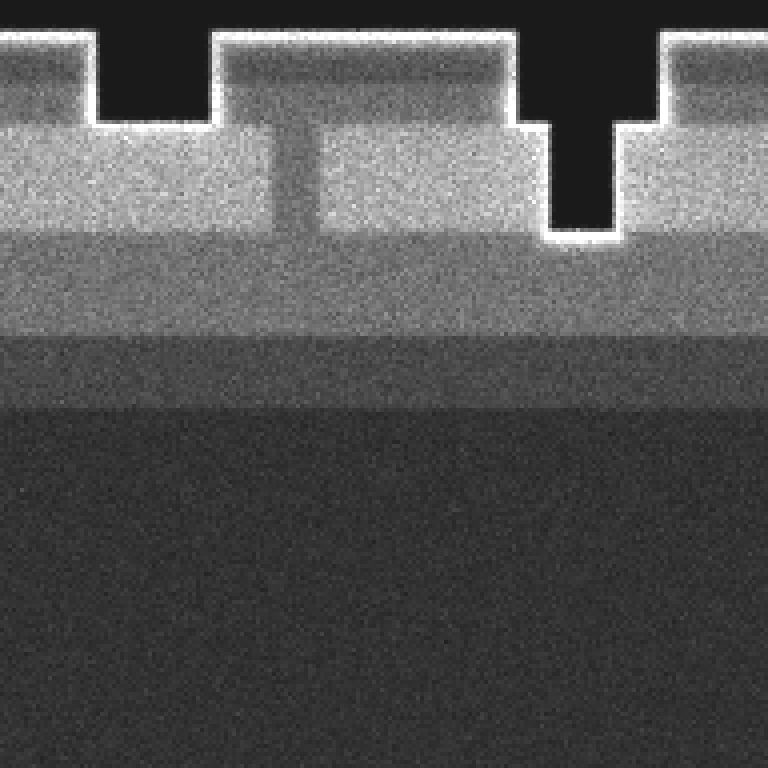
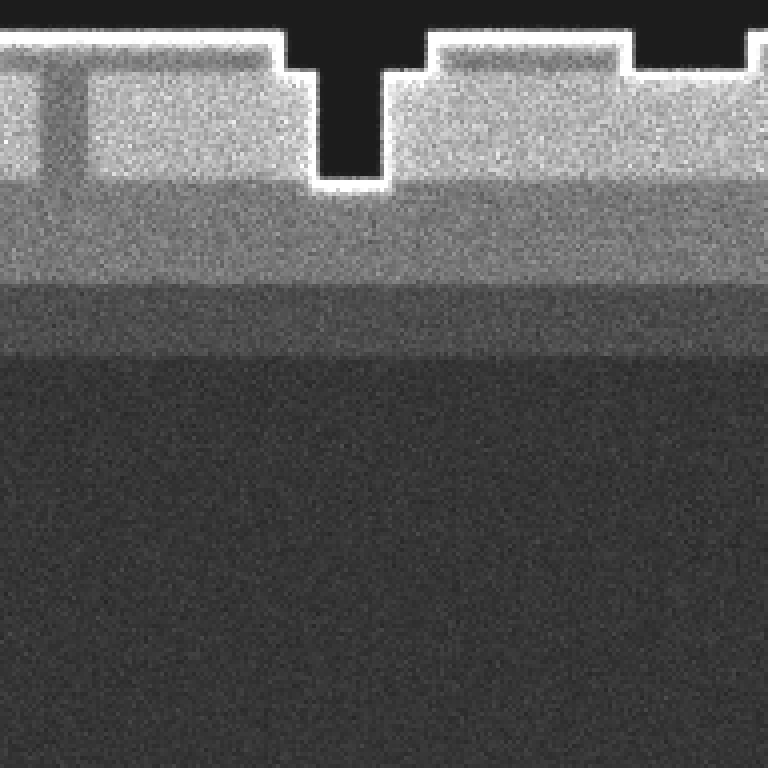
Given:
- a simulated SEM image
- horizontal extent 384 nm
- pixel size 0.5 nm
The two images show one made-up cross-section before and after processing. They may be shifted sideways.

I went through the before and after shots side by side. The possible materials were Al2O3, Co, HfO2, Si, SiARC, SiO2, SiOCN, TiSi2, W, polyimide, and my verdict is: removed, SiARC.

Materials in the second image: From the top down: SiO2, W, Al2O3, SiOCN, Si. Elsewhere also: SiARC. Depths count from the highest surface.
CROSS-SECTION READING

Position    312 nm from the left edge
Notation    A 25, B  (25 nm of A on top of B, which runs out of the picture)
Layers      SiO2 20, W 54, Al2O3 52, SiOCN 36, Si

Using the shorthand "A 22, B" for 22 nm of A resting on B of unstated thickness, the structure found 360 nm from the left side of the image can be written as empty 20, W 54, Al2O3 52, SiOCN 36, Si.